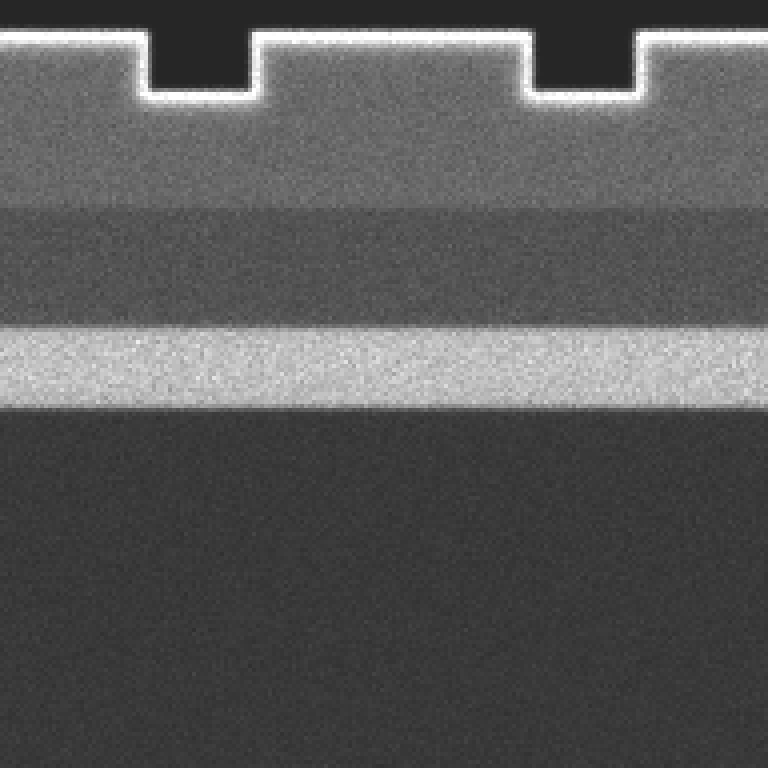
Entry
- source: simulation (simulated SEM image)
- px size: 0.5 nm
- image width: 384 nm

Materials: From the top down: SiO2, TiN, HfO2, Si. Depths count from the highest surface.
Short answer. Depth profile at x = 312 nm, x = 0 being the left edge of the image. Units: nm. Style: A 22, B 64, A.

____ empty 30, SiO2 58, TiN 60, HfO2 40, Si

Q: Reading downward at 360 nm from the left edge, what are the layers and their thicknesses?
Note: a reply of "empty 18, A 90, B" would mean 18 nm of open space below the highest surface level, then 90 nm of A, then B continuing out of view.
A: SiO2 88, TiN 60, HfO2 40, Si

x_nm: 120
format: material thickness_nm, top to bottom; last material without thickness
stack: empty 30, SiO2 58, TiN 60, HfO2 40, Si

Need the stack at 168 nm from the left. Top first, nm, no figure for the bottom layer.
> SiO2 88, TiN 60, HfO2 40, Si